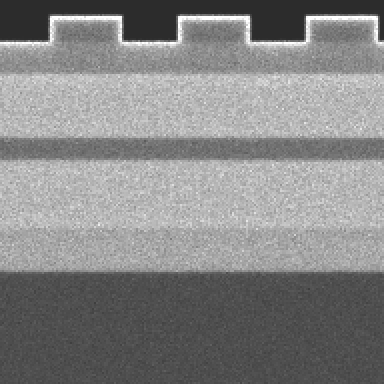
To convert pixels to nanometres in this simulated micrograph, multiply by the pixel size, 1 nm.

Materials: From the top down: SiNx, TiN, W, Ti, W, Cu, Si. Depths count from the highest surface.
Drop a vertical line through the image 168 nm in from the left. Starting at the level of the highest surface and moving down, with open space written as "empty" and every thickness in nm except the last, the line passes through empty 26, TiN 32, W 64, Ti 22, W 68, Cu 44, Si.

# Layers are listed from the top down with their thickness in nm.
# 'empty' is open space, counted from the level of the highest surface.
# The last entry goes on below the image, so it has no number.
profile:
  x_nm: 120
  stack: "SiNx 26, TiN 32, W 64, Ti 22, W 68, Cu 44, Si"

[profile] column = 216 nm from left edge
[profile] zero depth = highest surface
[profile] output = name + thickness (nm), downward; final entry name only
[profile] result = SiNx 26, TiN 32, W 64, Ti 22, W 68, Cu 44, Si